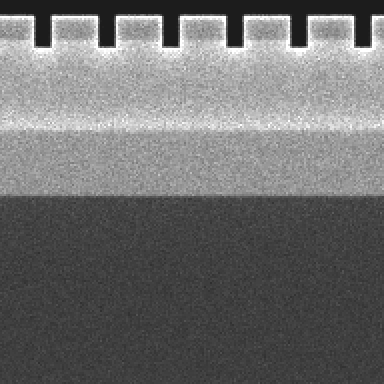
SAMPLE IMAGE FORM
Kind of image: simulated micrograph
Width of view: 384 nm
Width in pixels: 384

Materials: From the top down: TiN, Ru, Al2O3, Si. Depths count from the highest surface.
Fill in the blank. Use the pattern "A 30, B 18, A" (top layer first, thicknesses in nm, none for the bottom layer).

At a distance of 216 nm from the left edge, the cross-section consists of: TiN 24, Ru 90, Al2O3 66, Si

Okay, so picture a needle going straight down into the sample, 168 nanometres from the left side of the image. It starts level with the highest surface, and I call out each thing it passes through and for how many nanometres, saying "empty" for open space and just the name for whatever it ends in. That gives empty 32, Ru 82, Al2O3 66, Si